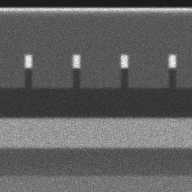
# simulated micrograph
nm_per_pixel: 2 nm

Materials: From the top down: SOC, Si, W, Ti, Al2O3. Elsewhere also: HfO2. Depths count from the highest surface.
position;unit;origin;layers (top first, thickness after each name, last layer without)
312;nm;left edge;SOC 160, Si 60, W 60, Ti 56, Al2O3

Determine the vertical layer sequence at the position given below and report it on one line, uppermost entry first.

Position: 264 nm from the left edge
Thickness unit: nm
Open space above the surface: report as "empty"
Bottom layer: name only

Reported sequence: SOC 160, Si 60, W 60, Ti 56, Al2O3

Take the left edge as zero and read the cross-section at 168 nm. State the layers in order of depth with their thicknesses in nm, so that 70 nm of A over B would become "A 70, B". SOC 160, Si 60, W 60, Ti 56, Al2O3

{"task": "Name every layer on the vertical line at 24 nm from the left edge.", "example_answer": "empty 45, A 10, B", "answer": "SOC 160, Si 60, W 60, Ti 56, Al2O3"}